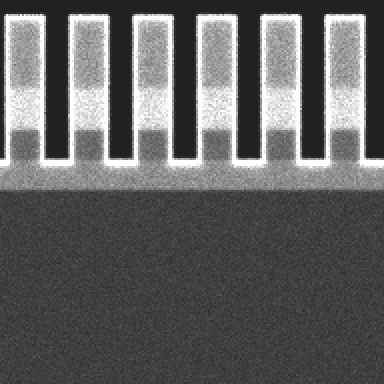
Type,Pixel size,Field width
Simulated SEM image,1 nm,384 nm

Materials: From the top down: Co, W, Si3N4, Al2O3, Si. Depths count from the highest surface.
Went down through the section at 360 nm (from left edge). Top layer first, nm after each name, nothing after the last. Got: Co 72, W 42, Si3N4 30, Al2O3 30, Si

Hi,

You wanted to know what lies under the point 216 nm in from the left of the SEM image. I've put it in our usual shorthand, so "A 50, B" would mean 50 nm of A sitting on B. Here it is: Co 72, W 42, Si3N4 30, Al2O3 30, Si